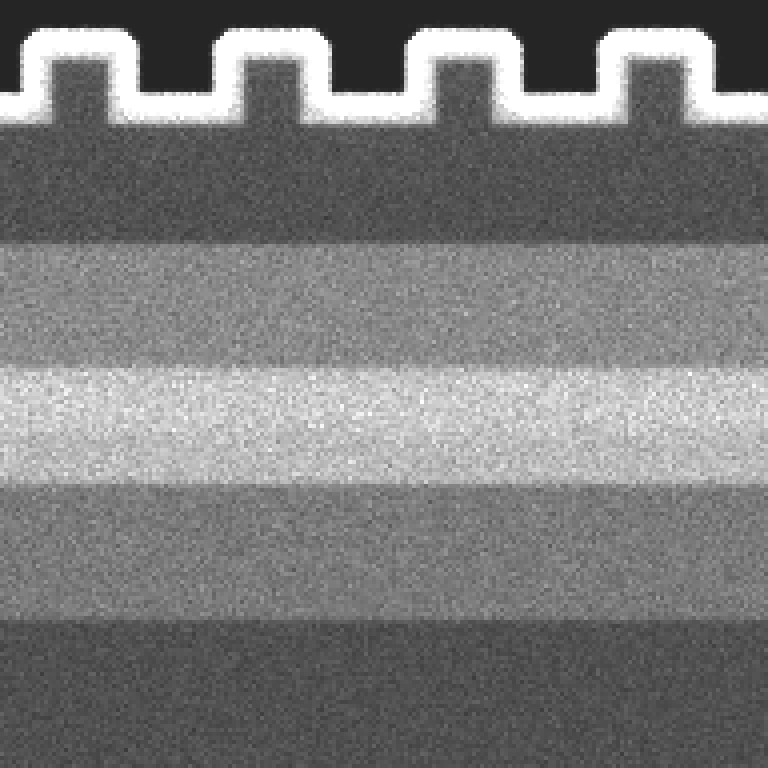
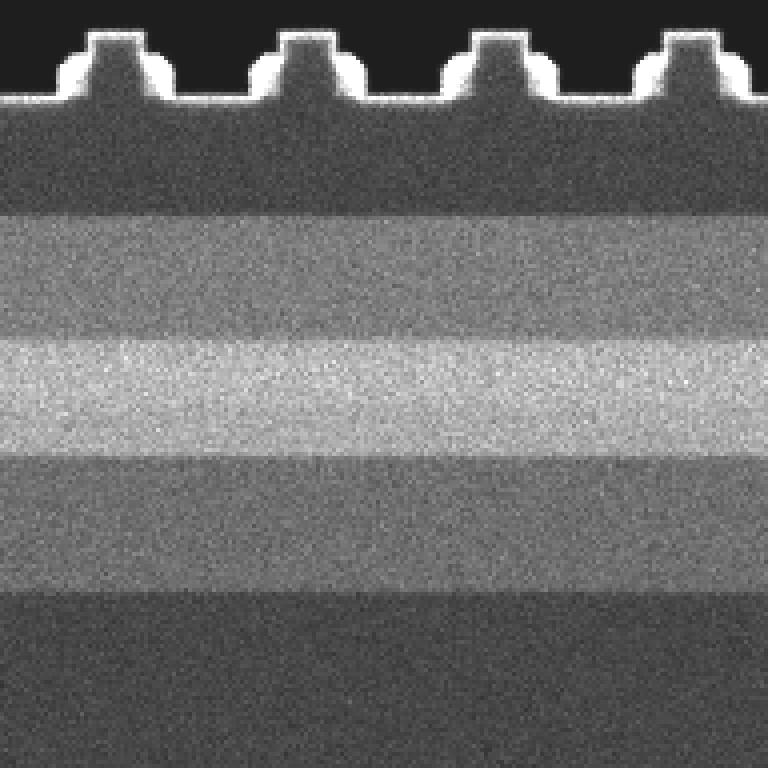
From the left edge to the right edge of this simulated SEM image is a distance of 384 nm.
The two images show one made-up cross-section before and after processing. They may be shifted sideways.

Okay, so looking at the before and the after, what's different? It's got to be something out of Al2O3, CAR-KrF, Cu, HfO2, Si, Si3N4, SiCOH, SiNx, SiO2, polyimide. Al2O3, removed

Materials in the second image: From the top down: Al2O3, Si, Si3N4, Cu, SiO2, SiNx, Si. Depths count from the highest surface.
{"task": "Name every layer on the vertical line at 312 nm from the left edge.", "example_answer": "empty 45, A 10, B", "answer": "empty 32, Si 60, Si3N4 62, Cu 32, SiO2 26, SiNx 68, Si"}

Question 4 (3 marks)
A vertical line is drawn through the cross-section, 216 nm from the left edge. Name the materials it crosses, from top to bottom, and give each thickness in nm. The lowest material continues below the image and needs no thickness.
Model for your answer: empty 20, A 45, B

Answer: empty 32, Si 60, Si3N4 62, Cu 32, SiO2 26, SiNx 68, Si